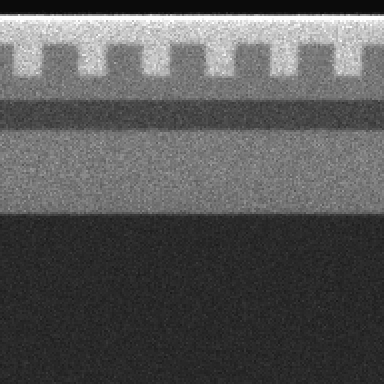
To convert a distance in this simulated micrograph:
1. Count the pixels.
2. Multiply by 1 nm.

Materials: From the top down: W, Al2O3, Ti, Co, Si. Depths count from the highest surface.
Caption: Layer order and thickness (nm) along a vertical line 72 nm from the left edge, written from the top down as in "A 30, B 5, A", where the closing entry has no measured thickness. W 28, Al2O3 56, Ti 30, Co 84, Si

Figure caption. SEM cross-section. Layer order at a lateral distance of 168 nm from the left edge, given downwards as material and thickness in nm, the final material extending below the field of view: W 60, Al2O3 24, Ti 30, Co 84, Si